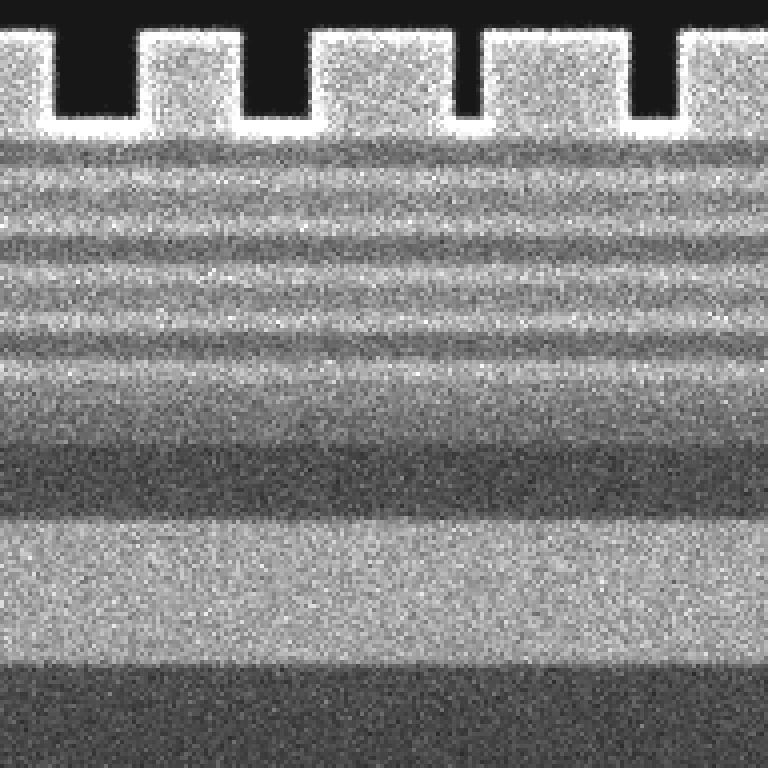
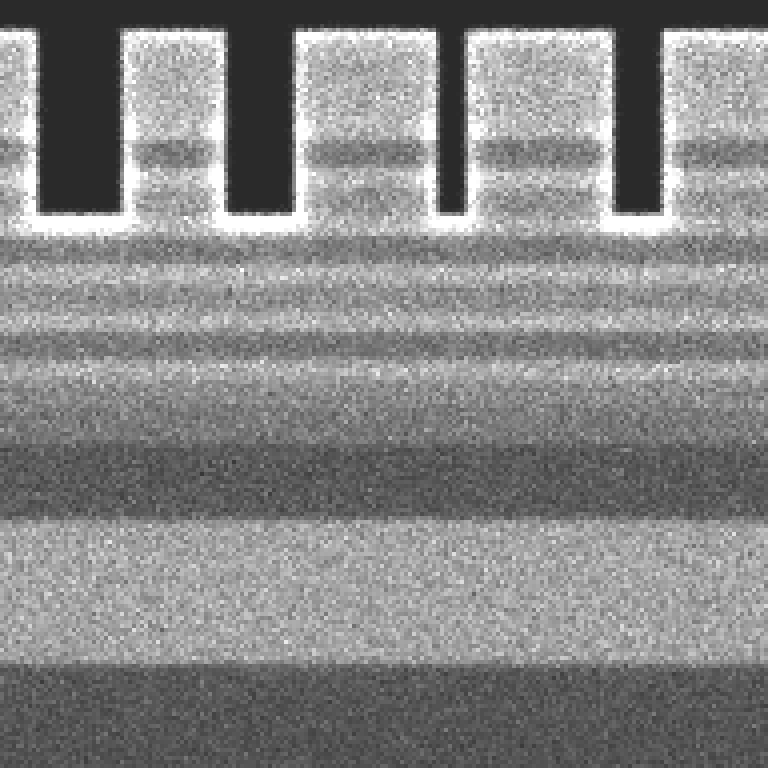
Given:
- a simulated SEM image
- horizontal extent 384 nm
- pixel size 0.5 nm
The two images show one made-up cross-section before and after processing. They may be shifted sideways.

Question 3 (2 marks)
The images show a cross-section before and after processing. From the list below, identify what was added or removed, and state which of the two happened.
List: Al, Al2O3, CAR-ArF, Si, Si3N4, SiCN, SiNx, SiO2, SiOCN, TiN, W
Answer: Al2O3 and Si3N4 and SiOCN was removed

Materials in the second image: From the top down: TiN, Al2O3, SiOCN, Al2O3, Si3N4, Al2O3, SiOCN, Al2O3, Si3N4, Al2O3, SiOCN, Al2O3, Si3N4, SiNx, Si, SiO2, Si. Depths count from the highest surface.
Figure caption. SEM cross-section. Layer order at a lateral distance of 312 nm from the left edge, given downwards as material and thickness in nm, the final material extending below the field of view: empty 92, Al2O3 10, SiOCN 14, Al2O3 10, Si3N4 14, Al2O3 10, SiOCN 14, Al2O3 10, Si3N4 14, SiNx 18, Si 38, SiO2 72, Si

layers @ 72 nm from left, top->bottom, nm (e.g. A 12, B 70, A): TiN 44, Al2O3 10, SiOCN 14, Al2O3 10, Si3N4 14, Al2O3 10, SiOCN 14, Al2O3 10, Si3N4 14, Al2O3 10, SiOCN 14, Al2O3 10, Si3N4 14, SiNx 18, Si 38, SiO2 72, Si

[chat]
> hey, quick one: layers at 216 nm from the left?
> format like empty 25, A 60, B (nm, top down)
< TiN 44, Al2O3 10, SiOCN 14, Al2O3 10, Si3N4 14, Al2O3 10, SiOCN 14, Al2O3 10, Si3N4 14, Al2O3 10, SiOCN 14, Al2O3 10, Si3N4 14, SiNx 18, Si 38, SiO2 72, Si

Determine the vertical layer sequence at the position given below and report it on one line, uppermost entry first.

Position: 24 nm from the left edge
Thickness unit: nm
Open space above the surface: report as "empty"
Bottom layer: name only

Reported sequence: empty 92, Al2O3 10, SiOCN 14, Al2O3 10, Si3N4 14, Al2O3 10, SiOCN 14, Al2O3 10, Si3N4 14, SiNx 18, Si 38, SiO2 72, Si